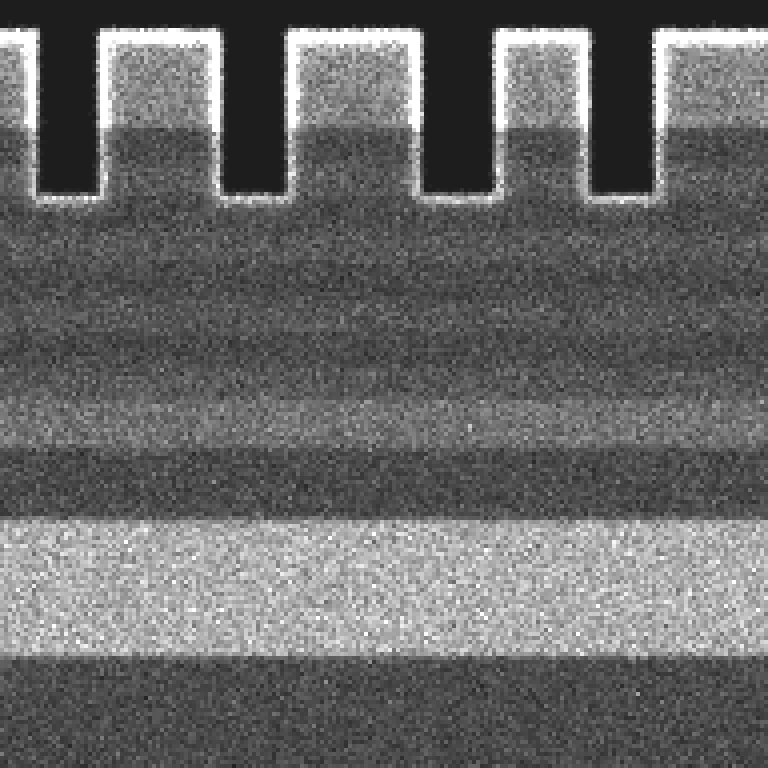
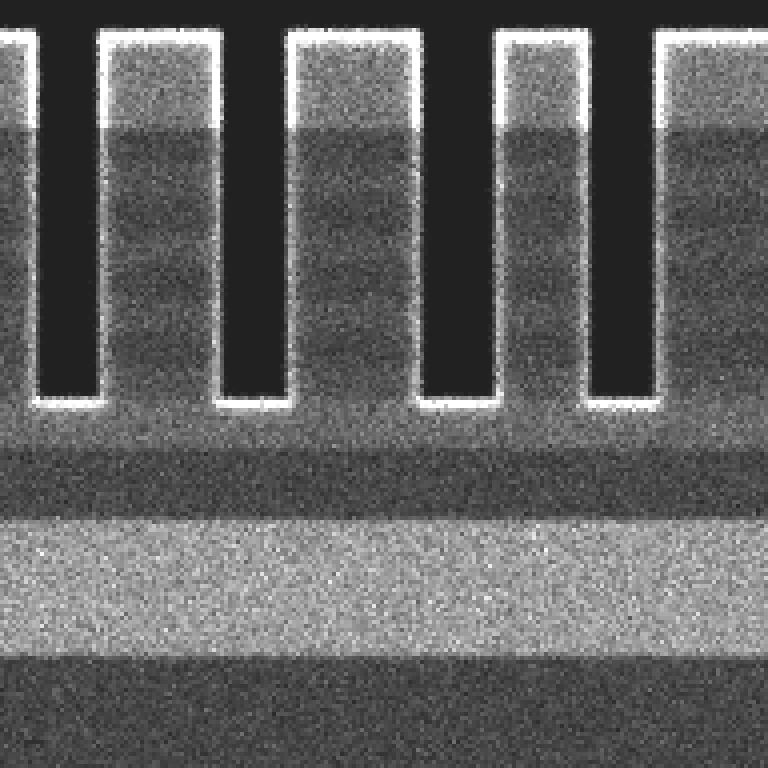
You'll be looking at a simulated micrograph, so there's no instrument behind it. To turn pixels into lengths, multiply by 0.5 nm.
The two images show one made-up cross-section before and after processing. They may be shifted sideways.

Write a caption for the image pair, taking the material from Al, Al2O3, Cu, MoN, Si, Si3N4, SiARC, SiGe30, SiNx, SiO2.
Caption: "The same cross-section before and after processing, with Si and SiGe30 removed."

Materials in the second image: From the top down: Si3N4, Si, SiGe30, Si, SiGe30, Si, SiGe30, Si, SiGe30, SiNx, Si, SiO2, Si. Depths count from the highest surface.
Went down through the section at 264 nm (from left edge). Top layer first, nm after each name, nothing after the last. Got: Si3N4 48, Si 18, SiGe30 16, Si 18, SiGe30 16, Si 18, SiGe30 16, Si 18, SiGe30 16, SiNx 24, Si 36, SiO2 68, Si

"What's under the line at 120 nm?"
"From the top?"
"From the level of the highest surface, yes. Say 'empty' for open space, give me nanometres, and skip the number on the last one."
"empty 184, SiNx 24, Si 36, SiO2 68, Si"